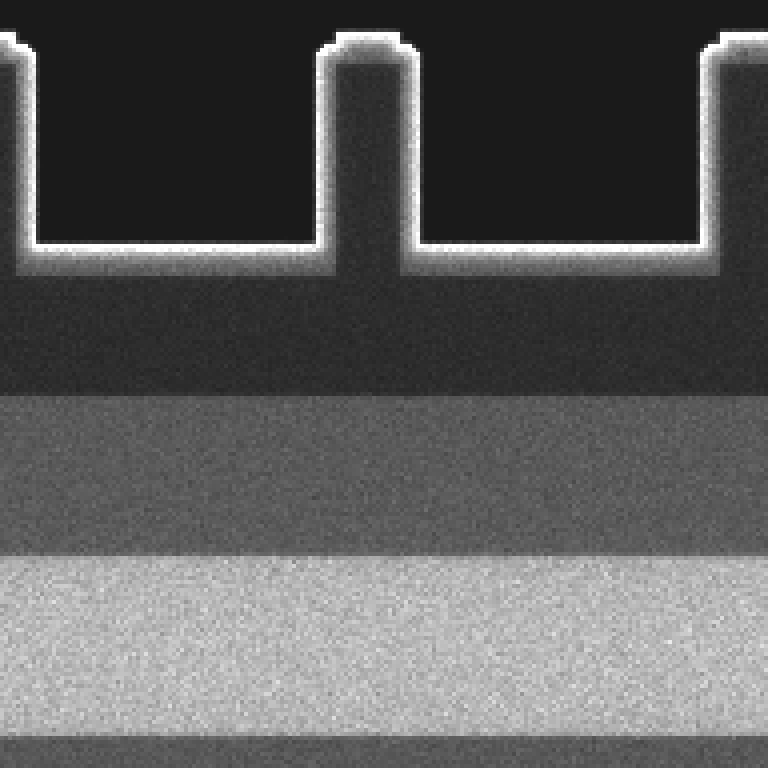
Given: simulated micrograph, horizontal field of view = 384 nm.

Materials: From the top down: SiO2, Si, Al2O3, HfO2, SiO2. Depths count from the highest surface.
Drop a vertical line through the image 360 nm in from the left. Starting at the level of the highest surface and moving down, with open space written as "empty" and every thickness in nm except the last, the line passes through SiO2 16, Si 166, Al2O3 80, HfO2 90, SiO2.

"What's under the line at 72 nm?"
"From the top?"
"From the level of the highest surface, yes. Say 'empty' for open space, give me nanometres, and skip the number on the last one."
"empty 106, SiO2 16, Si 60, Al2O3 80, HfO2 90, SiO2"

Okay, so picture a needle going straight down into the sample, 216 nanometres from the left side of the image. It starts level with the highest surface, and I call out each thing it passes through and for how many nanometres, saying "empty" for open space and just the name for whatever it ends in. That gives empty 106, SiO2 16, Si 60, Al2O3 80, HfO2 90, SiO2